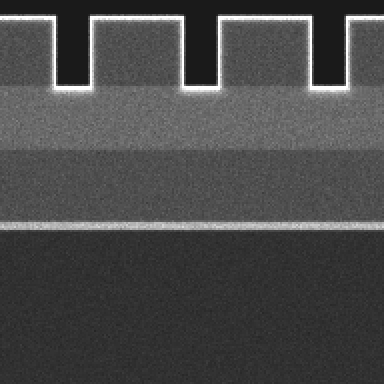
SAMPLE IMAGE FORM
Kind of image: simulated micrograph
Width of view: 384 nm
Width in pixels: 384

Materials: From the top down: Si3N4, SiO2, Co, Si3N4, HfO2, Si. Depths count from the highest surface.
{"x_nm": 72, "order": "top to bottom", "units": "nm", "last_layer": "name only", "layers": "empty 70, SiO2 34, Co 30, Si3N4 72, HfO2 8, Si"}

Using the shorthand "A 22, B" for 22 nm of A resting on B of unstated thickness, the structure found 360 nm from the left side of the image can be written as Si3N4 70, SiO2 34, Co 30, Si3N4 72, HfO2 8, Si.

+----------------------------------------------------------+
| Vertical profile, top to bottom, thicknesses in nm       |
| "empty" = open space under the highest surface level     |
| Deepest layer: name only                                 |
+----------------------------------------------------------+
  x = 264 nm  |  Si3N4 70, SiO2 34, Co 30, Si3N4 72, HfO2 8, Si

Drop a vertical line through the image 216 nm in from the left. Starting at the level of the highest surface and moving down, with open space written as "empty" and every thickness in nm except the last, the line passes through empty 70, SiO2 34, Co 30, Si3N4 72, HfO2 8, Si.